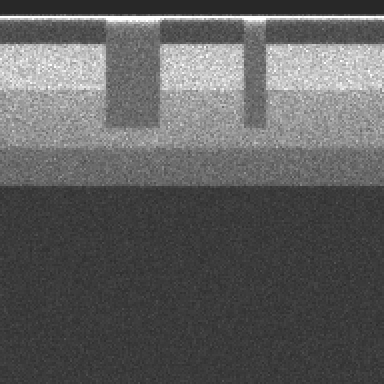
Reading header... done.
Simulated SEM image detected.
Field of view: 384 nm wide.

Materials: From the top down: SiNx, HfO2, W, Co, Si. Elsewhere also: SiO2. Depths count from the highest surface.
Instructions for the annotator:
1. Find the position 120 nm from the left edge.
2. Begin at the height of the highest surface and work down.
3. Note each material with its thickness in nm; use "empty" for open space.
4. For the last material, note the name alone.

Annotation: SiO2 112, W 20, Co 38, Si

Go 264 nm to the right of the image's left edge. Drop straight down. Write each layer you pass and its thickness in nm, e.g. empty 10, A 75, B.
SiO2 112, W 20, Co 38, Si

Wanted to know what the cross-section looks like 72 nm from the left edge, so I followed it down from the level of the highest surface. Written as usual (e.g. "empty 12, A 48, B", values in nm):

SiNx 28, HfO2 46, W 58, Co 38, Si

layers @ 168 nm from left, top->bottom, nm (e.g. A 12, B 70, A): SiNx 28, HfO2 46, W 58, Co 38, Si